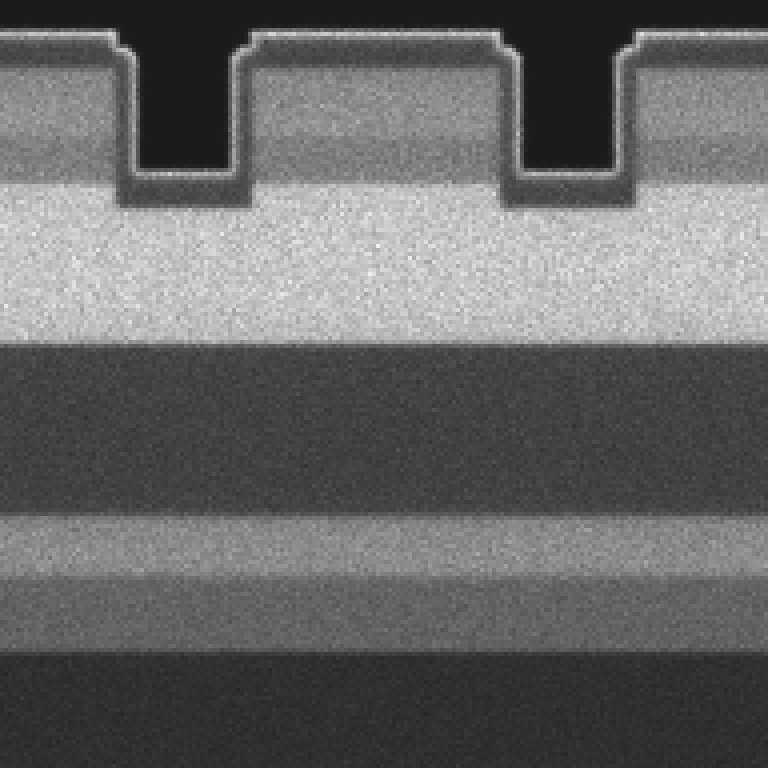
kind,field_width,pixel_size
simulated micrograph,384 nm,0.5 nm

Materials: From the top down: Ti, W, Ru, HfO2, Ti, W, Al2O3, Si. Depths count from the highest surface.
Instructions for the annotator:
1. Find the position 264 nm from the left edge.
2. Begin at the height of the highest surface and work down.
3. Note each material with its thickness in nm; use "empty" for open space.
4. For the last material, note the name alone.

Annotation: empty 70, Ti 18, HfO2 68, Ti 86, W 30, Al2O3 38, Si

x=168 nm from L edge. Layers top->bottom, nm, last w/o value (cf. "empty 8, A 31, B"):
Ti 18, W 34, Ru 24, HfO2 80, Ti 86, W 30, Al2O3 38, Si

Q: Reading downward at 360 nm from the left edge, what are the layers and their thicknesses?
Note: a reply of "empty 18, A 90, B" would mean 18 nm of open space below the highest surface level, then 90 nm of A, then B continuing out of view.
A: Ti 18, W 34, Ru 24, HfO2 80, Ti 86, W 30, Al2O3 38, Si